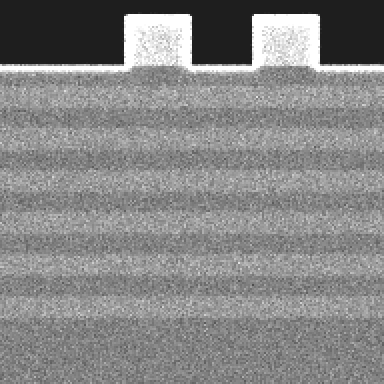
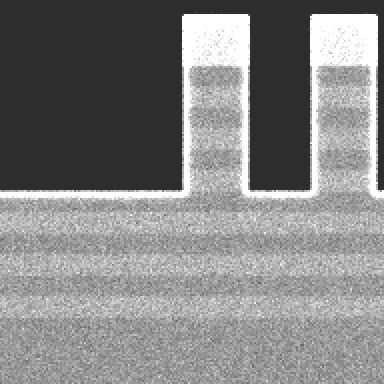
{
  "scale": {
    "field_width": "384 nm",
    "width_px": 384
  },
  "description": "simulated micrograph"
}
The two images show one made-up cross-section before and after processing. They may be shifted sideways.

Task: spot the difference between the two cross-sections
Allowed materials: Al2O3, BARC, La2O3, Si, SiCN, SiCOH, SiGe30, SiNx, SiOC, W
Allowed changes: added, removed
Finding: removed Si and SiGe30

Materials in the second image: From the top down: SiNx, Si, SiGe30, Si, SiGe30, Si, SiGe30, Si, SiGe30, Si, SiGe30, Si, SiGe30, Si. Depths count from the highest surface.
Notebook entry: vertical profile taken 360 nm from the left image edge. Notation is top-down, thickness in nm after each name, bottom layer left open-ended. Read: SiNx 50, Si 20, SiGe30 22, Si 20, SiGe30 22, Si 20, SiGe30 22, Si 20, SiGe30 22, Si 20, SiGe30 22, Si 20, SiGe30 22, Si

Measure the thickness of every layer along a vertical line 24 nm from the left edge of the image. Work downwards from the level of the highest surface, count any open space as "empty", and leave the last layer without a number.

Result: empty 176, Si 20, SiGe30 22, Si 20, SiGe30 22, Si 20, SiGe30 22, Si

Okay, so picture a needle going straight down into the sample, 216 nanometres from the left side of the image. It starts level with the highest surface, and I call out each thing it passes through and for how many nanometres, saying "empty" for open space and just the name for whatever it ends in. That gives SiNx 50, Si 20, SiGe30 22, Si 20, SiGe30 22, Si 20, SiGe30 22, Si 20, SiGe30 22, Si 20, SiGe30 22, Si 20, SiGe30 22, Si